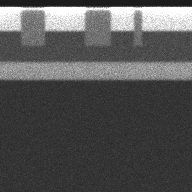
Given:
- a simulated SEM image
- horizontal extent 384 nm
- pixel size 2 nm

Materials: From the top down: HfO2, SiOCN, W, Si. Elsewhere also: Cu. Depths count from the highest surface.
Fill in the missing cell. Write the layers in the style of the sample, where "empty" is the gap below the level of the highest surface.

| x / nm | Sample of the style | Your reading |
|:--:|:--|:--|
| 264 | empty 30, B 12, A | HfO2 46, SiOCN 62, W 36, Si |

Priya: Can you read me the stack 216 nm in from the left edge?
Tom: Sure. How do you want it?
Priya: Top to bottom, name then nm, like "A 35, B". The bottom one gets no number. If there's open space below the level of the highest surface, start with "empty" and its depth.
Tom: Cu 76, SiOCN 32, W 36, Si